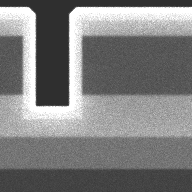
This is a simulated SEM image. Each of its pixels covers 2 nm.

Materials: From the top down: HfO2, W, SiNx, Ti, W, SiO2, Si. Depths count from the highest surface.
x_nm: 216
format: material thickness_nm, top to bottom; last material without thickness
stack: HfO2 24, W 32, SiNx 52, Ti 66, W 84, SiO2 64, Si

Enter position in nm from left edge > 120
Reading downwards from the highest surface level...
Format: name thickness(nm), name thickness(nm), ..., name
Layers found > empty 198, HfO2 24, W 36, SiO2 64, Si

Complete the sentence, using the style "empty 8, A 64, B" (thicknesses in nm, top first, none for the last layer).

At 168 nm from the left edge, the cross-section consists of HfO2 24, W 32, SiNx 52, Ti 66, W 84, SiO2 64, Si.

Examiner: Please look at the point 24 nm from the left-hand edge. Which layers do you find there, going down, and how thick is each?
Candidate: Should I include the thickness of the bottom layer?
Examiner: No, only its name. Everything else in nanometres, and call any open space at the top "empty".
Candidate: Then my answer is HfO2 24, W 32, SiNx 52, Ti 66, W 84, SiO2 64, Si